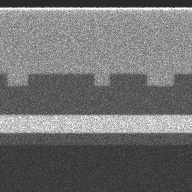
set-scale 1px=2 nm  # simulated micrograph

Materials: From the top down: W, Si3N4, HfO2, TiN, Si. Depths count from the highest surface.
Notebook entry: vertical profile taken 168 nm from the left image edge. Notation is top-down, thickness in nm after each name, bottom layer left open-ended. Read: W 132, Si3N4 82, HfO2 36, TiN 24, Si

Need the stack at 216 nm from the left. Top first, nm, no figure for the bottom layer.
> W 156, Si3N4 58, HfO2 36, TiN 24, Si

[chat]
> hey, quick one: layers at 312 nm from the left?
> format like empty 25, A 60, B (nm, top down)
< W 156, Si3N4 58, HfO2 36, TiN 24, Si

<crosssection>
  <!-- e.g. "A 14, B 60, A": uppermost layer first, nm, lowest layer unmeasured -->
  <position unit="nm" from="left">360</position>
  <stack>W 132, Si3N4 82, HfO2 36, TiN 24, Si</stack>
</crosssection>